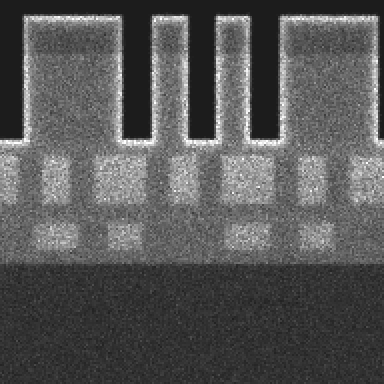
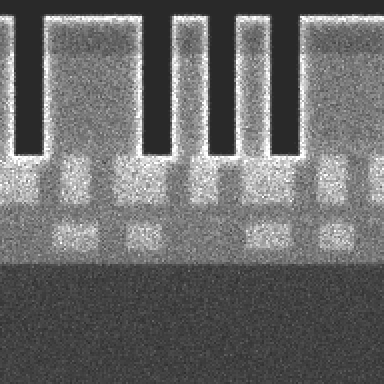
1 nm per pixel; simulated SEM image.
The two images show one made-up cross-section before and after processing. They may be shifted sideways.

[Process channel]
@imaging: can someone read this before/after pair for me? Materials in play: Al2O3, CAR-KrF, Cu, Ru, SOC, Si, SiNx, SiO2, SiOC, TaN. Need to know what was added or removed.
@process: Al2O3 removed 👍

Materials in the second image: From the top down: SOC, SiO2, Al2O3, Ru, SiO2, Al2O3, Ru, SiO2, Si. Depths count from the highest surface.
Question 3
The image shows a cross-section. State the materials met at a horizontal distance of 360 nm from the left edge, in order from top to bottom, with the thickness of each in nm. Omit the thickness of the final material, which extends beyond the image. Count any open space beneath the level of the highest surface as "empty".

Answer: SOC 38, SiO2 86, Al2O3 16, SiO2 60, Al2O3 8, SiO2 40, Si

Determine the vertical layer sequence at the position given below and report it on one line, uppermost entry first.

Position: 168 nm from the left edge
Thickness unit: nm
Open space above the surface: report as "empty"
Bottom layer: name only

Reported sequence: empty 140, SiO2 60, Al2O3 8, SiO2 40, Si